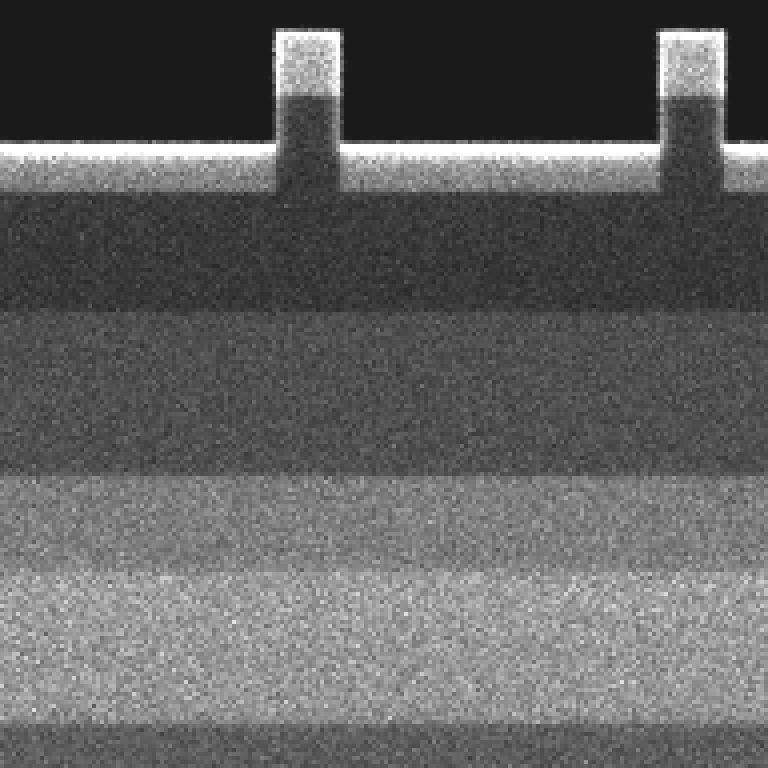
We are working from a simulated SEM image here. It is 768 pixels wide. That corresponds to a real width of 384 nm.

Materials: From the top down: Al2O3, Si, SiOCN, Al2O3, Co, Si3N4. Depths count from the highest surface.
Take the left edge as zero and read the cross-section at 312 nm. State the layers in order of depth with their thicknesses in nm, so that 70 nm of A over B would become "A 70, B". empty 56, Al2O3 24, Si 60, SiOCN 82, Al2O3 48, Co 76, Si3N4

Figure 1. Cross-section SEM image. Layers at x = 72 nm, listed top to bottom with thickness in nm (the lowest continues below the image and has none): empty 56, Al2O3 24, Si 60, SiOCN 82, Al2O3 48, Co 76, Si3N4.